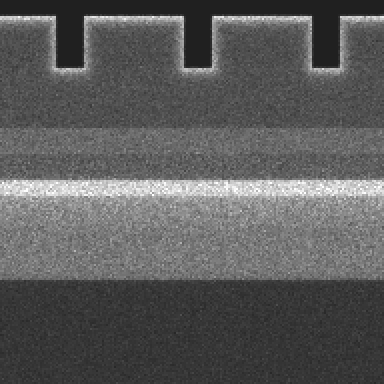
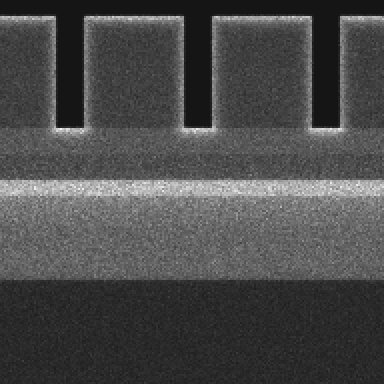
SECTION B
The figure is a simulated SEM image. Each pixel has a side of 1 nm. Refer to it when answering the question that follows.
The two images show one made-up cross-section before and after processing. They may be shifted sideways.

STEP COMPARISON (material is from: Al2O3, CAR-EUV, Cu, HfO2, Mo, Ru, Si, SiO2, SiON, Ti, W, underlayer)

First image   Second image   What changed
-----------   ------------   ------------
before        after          underlayer, removed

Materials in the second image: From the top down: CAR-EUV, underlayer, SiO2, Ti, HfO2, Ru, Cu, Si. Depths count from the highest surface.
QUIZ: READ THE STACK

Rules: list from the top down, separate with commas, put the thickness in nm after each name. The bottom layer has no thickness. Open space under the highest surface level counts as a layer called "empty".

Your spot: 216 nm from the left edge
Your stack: CAR-EUV 52, underlayer 60, SiO2 26, Ti 26, HfO2 16, Ru 30, Cu 54, Si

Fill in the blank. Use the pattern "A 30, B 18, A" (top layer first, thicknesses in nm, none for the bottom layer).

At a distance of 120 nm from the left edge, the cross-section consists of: CAR-EUV 52, underlayer 60, SiO2 26, Ti 26, HfO2 16, Ru 30, Cu 54, Si